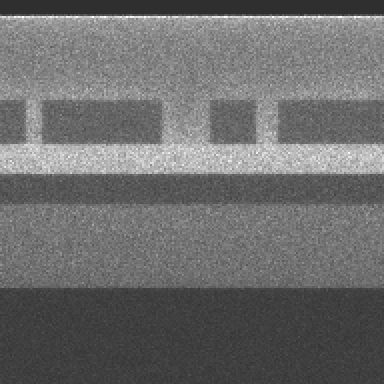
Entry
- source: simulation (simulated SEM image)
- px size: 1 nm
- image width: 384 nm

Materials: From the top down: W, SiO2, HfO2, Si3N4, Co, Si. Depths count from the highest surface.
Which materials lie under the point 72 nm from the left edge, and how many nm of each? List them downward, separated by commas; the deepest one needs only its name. W 84, SiO2 44, HfO2 30, Si3N4 30, Co 84, Si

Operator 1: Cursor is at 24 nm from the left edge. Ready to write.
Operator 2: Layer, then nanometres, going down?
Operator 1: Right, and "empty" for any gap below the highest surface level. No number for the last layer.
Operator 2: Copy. W 84, SiO2 44, HfO2 30, Si3N4 30, Co 84, Si